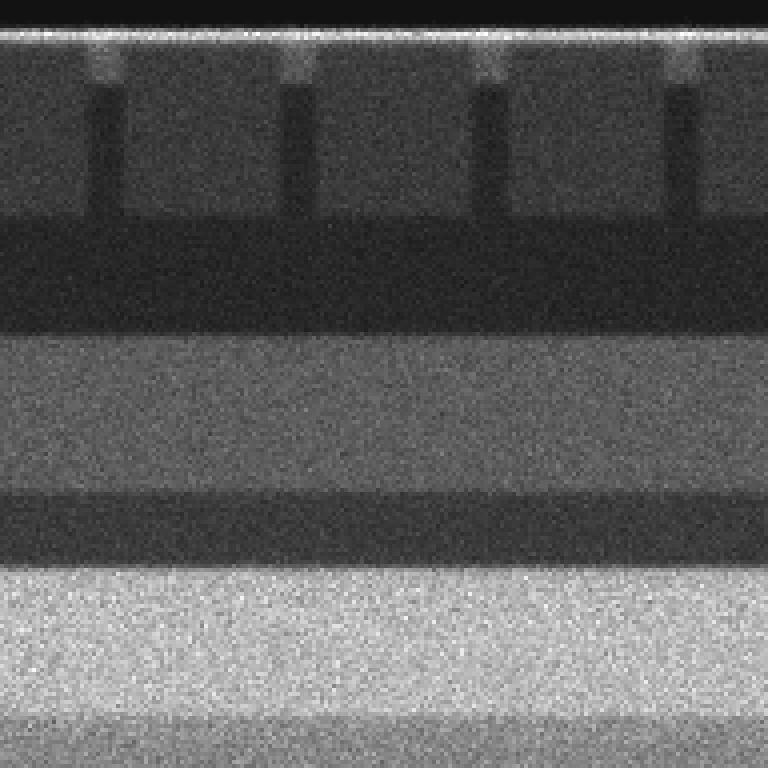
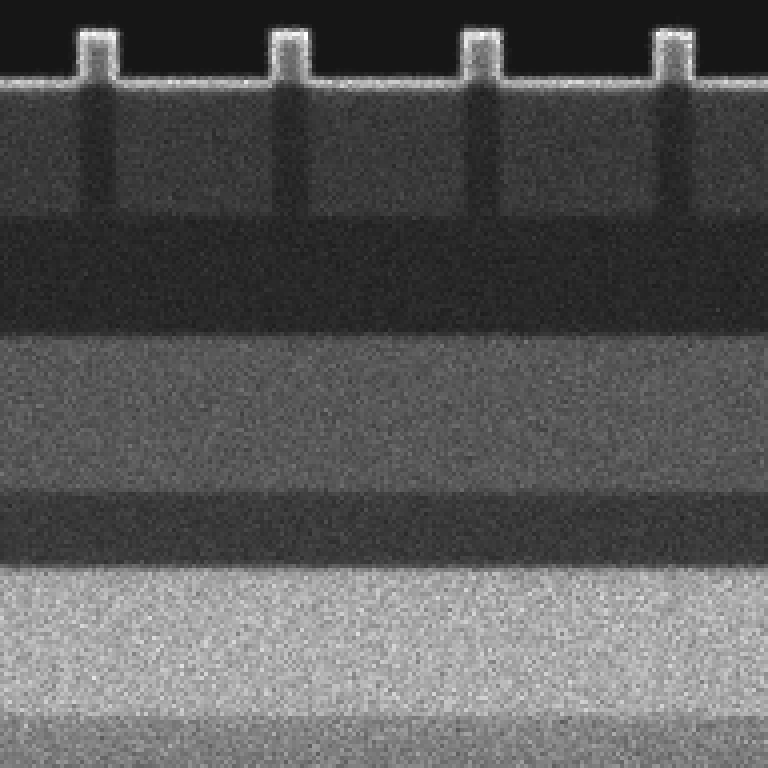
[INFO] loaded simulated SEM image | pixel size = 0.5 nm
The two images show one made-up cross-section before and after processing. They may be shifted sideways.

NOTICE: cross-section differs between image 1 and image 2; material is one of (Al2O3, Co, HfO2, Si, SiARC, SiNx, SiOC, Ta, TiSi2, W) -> removed: SiNx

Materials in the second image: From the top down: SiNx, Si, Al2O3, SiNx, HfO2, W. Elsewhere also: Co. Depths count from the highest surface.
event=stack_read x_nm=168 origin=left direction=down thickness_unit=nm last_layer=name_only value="empty 24, SiNx 68, Si 60, Al2O3 78, SiNx 38, HfO2 74, W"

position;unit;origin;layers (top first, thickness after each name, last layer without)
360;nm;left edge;empty 24, SiNx 68, Si 60, Al2O3 78, SiNx 38, HfO2 74, W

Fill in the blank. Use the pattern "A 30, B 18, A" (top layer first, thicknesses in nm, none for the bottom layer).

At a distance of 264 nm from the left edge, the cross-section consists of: empty 24, SiNx 68, Si 60, Al2O3 78, SiNx 38, HfO2 74, W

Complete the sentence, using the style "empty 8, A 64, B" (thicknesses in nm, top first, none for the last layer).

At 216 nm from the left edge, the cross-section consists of empty 24, SiNx 68, Si 60, Al2O3 78, SiNx 38, HfO2 74, W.